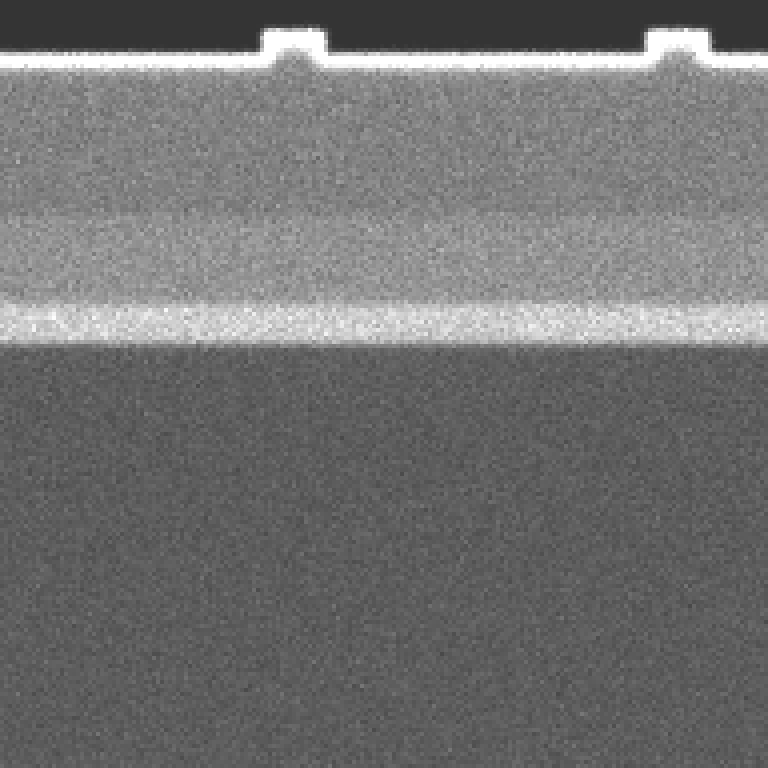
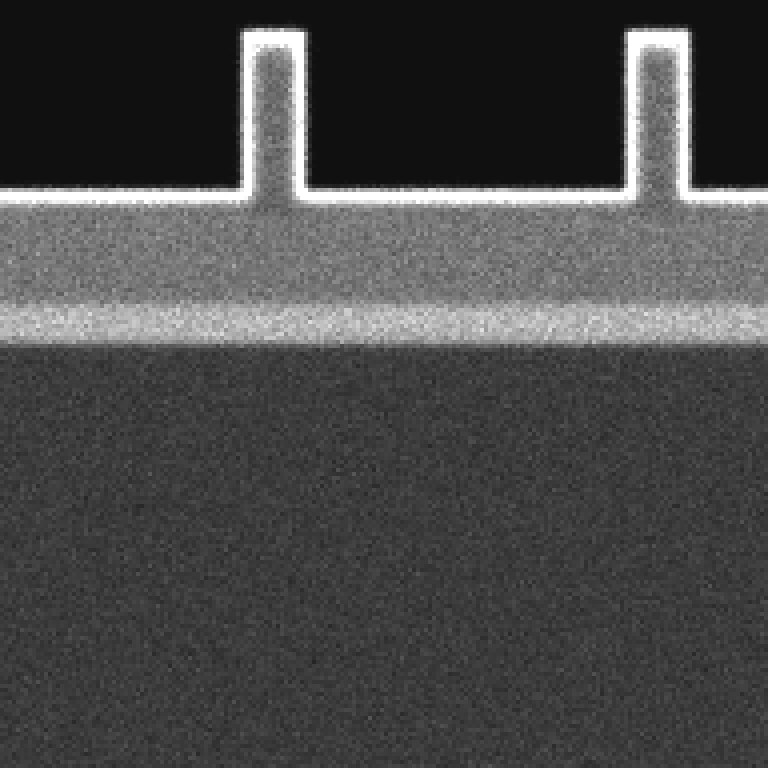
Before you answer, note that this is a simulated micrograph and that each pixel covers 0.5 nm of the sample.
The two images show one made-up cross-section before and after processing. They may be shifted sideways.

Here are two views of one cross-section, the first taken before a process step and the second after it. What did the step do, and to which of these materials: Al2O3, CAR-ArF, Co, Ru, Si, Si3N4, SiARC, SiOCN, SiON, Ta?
It removed SiOCN.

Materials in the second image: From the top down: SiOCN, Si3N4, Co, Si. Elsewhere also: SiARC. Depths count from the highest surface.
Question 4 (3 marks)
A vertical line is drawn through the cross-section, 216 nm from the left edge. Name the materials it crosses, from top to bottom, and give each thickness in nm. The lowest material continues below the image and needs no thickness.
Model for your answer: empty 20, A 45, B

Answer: empty 80, SiOCN 12, Si3N4 44, Co 20, Si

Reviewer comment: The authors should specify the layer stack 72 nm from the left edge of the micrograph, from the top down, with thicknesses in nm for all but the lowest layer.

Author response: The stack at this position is empty 80, SiOCN 12, Si3N4 44, Co 20, Si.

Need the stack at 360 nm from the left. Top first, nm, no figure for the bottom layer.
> empty 80, SiOCN 12, Si3N4 44, Co 20, Si